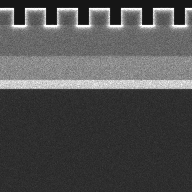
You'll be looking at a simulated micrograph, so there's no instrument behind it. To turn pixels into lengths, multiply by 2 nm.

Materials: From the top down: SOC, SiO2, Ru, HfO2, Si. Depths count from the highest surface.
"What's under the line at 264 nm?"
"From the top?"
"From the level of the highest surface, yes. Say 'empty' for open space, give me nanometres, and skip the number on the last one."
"SOC 34, SiO2 62, Ru 48, HfO2 18, Si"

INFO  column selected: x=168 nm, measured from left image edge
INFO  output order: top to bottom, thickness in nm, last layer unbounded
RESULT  empty 34, SiO2 62, Ru 48, HfO2 18, Si